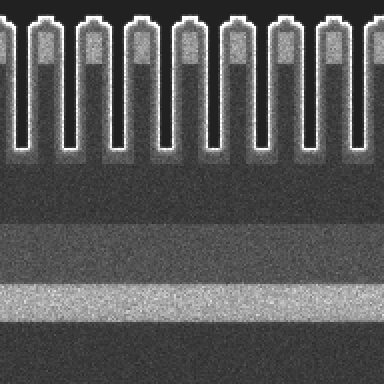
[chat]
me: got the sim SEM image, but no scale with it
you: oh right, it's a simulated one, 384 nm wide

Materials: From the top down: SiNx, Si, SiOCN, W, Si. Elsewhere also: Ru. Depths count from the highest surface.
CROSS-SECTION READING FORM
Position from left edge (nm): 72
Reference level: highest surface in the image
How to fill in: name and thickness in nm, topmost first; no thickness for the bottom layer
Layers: empty 132, SiNx 16, Si 60, SiOCN 60, W 38, Si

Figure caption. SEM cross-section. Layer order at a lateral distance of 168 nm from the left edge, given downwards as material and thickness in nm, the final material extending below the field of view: empty 132, SiNx 16, Si 60, SiOCN 60, W 38, Si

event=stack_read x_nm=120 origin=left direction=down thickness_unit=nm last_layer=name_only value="empty 132, SiNx 16, Si 60, SiOCN 60, W 38, Si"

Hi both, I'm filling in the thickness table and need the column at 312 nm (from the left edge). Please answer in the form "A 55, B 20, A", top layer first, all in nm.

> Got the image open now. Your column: empty 132, SiNx 16, Si 60, SiOCN 60, W 38, Si